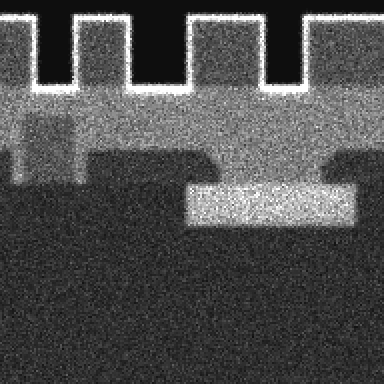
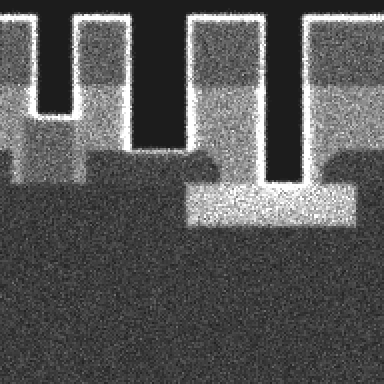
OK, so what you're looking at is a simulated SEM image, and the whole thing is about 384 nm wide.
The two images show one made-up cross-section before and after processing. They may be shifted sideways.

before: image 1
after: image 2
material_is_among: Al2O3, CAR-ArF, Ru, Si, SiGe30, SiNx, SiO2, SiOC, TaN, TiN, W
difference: SiO2, removed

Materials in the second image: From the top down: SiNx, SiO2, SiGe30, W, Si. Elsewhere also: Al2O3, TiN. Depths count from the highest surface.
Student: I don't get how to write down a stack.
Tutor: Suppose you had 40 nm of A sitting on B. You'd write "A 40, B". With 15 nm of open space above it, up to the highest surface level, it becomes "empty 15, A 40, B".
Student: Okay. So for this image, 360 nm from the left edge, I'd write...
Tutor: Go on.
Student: SiNx 70, SiO2 64, SiGe30 34, Si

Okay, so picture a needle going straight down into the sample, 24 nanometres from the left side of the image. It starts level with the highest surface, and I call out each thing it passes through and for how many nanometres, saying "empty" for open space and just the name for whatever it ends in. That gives SiNx 70, SiO2 30, TiN 68, Si